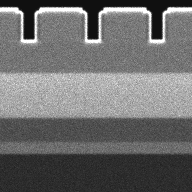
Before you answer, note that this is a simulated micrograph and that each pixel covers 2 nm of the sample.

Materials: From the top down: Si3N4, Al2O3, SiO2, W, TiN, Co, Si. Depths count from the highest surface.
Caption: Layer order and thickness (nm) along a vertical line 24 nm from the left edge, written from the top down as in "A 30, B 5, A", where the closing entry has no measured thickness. Al2O3 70, SiO2 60, W 90, TiN 48, Co 24, Si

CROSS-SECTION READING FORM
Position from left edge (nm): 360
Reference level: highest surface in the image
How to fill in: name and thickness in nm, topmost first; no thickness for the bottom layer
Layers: Al2O3 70, SiO2 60, W 90, TiN 48, Co 24, Si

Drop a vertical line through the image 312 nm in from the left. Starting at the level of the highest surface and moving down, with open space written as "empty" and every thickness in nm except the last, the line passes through empty 64, Al2O3 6, SiO2 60, W 90, TiN 48, Co 24, Si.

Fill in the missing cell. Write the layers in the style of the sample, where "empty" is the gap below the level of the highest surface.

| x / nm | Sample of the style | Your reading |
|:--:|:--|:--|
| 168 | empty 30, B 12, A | empty 6, Si3N4 58, Al2O3 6, SiO2 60, W 90, TiN 48, Co 24, Si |